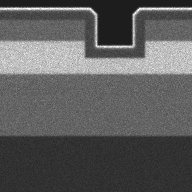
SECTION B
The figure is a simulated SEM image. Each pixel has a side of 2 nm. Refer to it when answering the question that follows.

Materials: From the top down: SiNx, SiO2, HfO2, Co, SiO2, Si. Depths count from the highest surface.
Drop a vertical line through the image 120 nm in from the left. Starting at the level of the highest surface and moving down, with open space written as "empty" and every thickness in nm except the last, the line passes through SiNx 24, SiO2 42, HfO2 66, Co 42, SiO2 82, Si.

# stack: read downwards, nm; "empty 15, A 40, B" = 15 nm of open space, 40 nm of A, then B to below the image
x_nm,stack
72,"SiNx 24, SiO2 42, HfO2 66, Co 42, SiO2 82, Si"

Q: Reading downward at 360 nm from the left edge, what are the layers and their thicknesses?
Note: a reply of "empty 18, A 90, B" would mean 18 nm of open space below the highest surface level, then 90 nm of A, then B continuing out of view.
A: SiNx 24, SiO2 42, HfO2 66, Co 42, SiO2 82, Si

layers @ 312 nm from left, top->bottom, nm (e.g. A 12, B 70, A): SiNx 24, SiO2 42, HfO2 66, Co 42, SiO2 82, Si